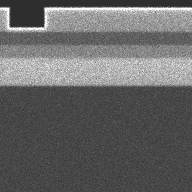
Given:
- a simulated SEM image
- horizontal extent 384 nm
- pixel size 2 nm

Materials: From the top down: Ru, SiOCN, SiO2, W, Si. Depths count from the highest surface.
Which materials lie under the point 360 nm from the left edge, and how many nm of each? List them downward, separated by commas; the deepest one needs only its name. Ru 48, SiOCN 26, SiO2 26, W 56, Si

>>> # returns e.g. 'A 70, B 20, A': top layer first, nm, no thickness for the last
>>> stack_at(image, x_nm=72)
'empty 40, Ru 8, SiOCN 26, SiO2 26, W 56, Si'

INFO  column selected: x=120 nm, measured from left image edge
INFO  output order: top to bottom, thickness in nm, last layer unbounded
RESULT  Ru 48, SiOCN 26, SiO2 26, W 56, Si